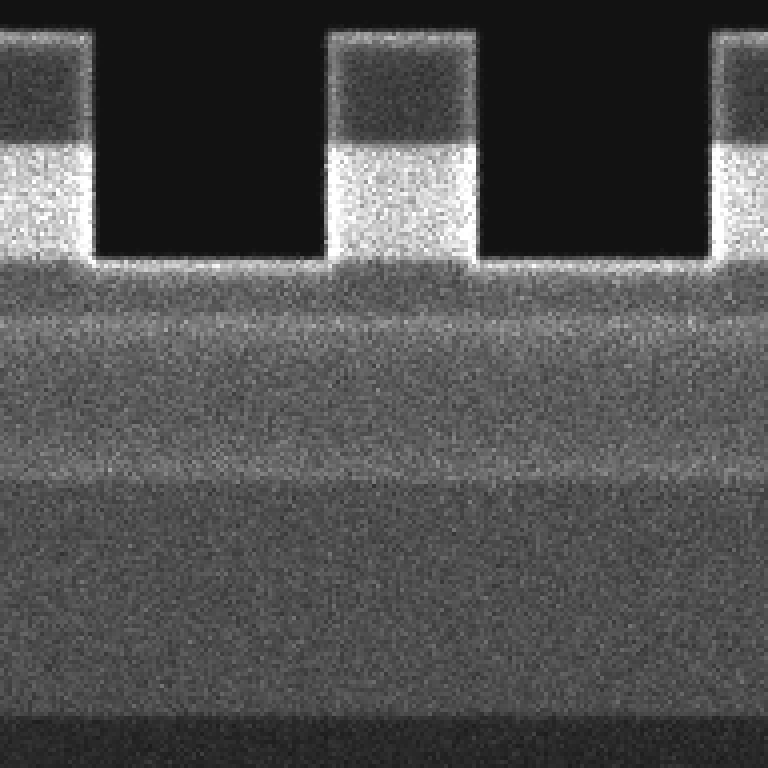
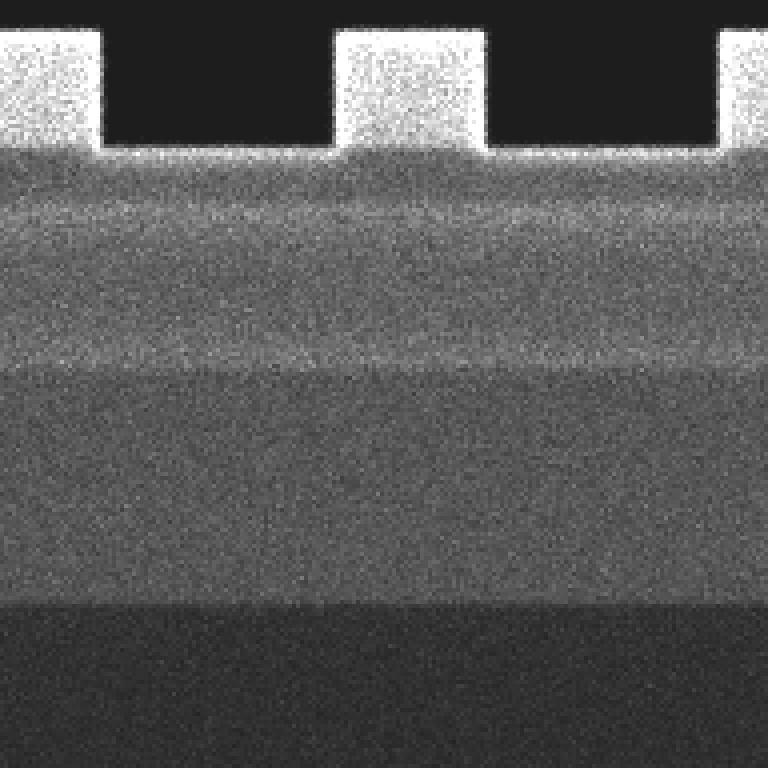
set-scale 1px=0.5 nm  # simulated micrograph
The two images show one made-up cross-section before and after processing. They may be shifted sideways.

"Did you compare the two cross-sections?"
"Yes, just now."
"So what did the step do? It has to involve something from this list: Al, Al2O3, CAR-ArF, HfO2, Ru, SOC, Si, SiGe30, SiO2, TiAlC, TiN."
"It removed SOC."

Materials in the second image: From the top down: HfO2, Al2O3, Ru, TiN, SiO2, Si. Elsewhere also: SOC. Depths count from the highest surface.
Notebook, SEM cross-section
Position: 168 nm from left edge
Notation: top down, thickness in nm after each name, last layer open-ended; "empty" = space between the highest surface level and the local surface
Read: HfO2 58, Al2O3 28, Ru 82, TiN 10, SiO2 108, Si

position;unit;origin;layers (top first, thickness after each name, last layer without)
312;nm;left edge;empty 58, Al2O3 28, Ru 82, TiN 10, SiO2 108, Si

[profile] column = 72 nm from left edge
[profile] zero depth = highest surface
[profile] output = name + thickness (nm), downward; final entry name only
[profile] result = empty 58, Al2O3 28, Ru 82, TiN 10, SiO2 108, Si